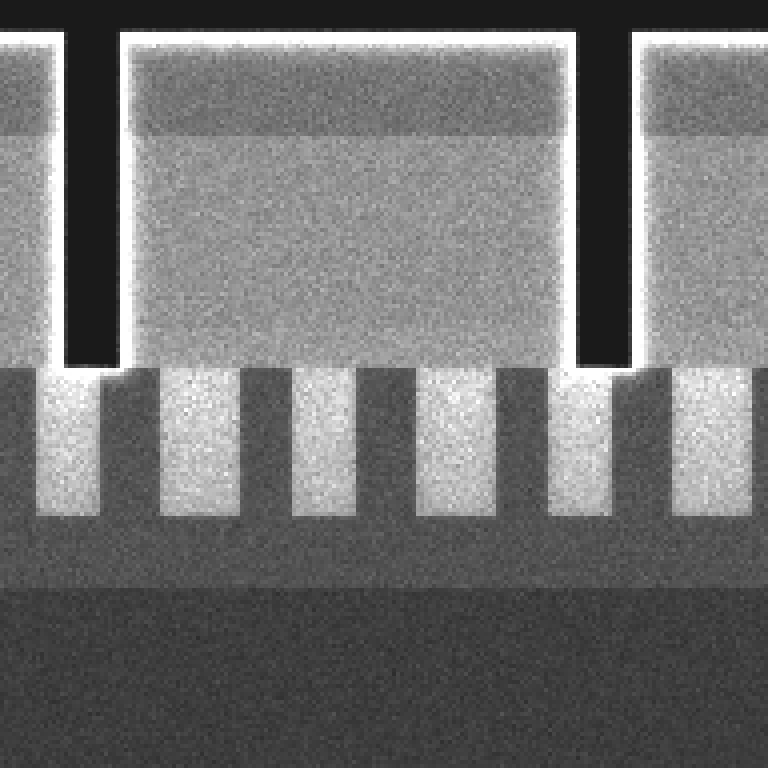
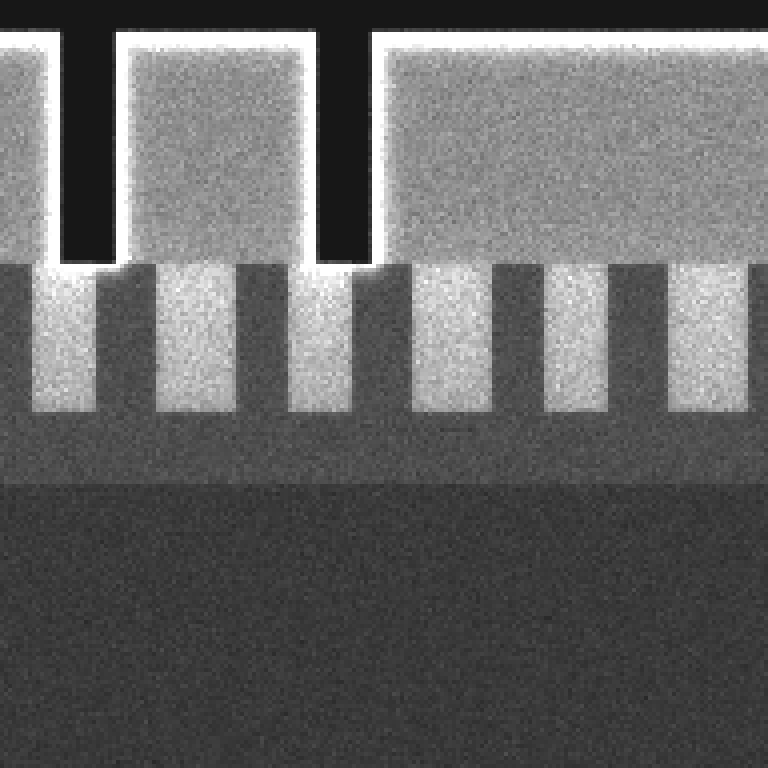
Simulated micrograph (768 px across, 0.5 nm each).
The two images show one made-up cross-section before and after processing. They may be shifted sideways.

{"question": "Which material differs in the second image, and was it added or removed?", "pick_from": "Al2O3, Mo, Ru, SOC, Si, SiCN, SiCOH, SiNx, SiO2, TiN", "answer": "SOC, removed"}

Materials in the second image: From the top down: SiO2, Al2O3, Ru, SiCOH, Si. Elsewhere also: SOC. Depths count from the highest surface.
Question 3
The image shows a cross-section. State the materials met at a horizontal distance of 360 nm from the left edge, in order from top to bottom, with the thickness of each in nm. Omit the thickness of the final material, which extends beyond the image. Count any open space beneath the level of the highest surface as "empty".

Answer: SiO2 96, Al2O3 20, Ru 74, SiCOH 36, Si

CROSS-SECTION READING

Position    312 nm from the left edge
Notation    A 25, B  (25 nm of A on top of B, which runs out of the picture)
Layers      SiO2 96, Al2O3 20, SiCOH 110, Si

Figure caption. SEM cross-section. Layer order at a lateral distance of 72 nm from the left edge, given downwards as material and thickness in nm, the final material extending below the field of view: SiO2 96, Al2O3 20, SiCOH 110, Si